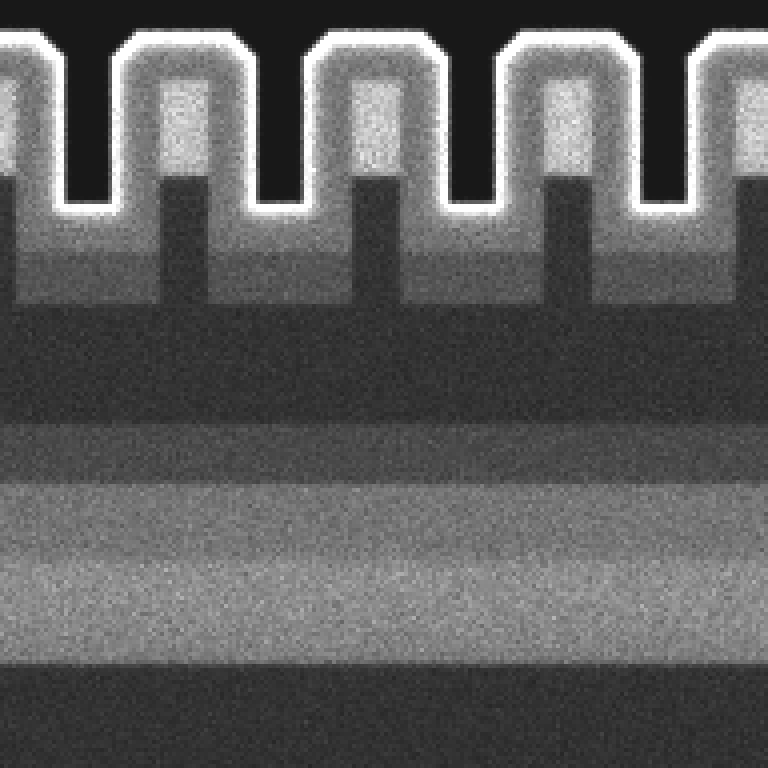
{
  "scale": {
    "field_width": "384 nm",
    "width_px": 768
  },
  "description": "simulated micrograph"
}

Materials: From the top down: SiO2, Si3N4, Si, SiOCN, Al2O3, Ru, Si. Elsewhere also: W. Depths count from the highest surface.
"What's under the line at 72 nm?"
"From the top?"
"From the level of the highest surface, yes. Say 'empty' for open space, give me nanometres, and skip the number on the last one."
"SiO2 110, Si3N4 26, Si 60, SiOCN 30, Al2O3 38, Ru 52, Si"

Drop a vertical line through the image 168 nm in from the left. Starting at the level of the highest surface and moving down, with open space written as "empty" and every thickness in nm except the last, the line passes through SiO2 110, Si3N4 26, Si 60, SiOCN 30, Al2O3 38, Ru 52, Si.